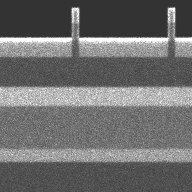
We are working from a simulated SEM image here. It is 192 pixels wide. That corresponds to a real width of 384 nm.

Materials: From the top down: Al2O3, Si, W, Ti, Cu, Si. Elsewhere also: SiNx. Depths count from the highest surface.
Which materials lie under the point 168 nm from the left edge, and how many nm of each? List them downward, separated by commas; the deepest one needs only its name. empty 60, Al2O3 38, Si 60, W 38, Ti 86, Cu 26, Si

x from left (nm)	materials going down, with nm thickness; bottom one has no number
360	empty 60, Al2O3 38, Si 60, W 38, Ti 86, Cu 26, Si